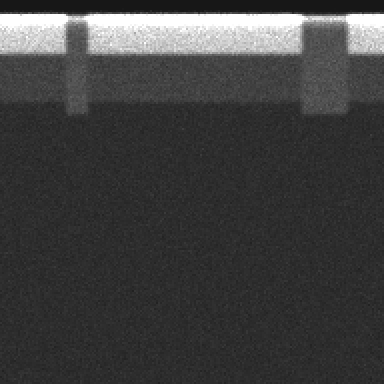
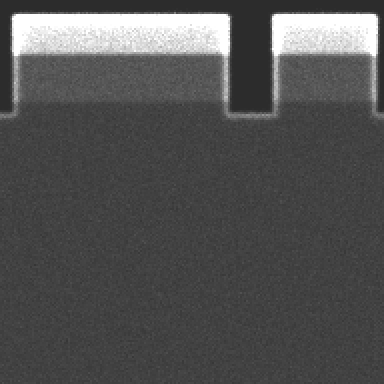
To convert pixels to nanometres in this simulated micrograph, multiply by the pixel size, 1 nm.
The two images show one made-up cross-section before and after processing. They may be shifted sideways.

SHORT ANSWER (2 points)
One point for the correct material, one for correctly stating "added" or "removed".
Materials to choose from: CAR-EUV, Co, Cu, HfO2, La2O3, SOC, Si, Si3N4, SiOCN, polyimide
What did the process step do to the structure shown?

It removed SOC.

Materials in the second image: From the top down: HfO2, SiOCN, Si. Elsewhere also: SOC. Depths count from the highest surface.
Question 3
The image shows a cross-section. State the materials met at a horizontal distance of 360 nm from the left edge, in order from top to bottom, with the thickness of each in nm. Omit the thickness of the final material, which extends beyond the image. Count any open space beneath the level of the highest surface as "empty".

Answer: HfO2 38, SiOCN 48, Si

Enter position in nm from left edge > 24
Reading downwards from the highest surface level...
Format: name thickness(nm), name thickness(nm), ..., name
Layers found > HfO2 38, SiOCN 48, Si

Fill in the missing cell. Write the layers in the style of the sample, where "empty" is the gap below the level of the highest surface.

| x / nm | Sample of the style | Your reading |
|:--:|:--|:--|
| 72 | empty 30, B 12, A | HfO2 38, SiOCN 48, Si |